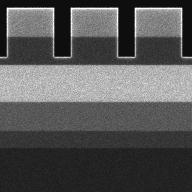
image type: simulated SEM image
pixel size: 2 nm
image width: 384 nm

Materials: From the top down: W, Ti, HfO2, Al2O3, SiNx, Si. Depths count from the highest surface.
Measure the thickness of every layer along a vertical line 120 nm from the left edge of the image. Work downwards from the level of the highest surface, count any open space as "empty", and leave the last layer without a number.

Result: empty 98, Ti 16, HfO2 74, Al2O3 58, SiNx 34, Si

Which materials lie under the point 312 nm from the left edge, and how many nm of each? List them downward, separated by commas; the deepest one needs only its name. W 58, Ti 56, HfO2 74, Al2O3 58, SiNx 34, Si